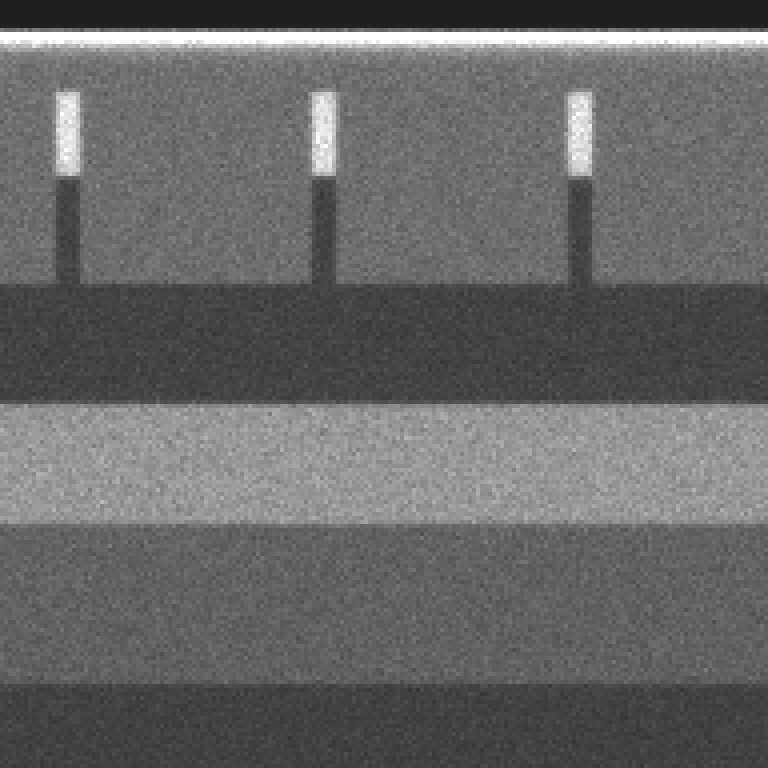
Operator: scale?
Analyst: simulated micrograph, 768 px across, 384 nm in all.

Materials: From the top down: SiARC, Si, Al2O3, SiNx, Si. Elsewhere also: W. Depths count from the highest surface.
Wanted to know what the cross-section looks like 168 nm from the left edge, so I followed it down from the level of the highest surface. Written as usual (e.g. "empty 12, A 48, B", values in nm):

SiARC 126, Si 60, Al2O3 60, SiNx 80, Si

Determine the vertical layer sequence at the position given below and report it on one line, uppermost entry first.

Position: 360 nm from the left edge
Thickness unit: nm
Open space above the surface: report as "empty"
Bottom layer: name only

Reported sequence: SiARC 126, Si 60, Al2O3 60, SiNx 80, Si